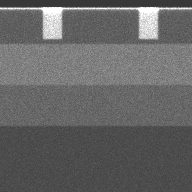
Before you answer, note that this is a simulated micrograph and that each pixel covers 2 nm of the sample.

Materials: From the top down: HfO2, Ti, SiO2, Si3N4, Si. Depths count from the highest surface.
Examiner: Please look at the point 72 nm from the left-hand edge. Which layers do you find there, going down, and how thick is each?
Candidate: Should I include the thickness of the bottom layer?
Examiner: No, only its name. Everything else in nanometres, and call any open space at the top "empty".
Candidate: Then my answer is Ti 72, SiO2 82, Si3N4 82, Si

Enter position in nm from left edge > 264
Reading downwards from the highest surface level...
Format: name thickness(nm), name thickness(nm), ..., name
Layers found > Ti 72, SiO2 82, Si3N4 82, Si